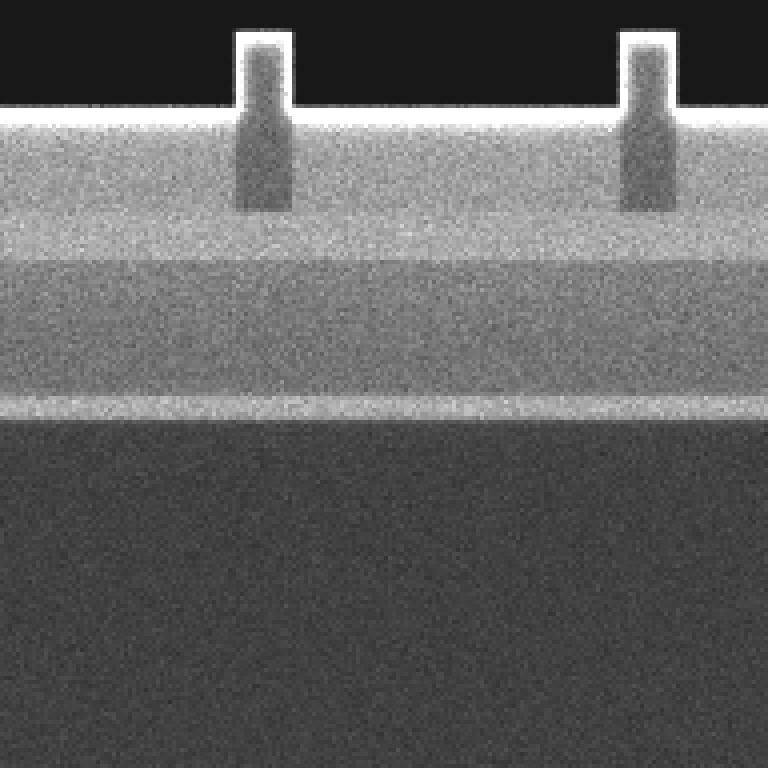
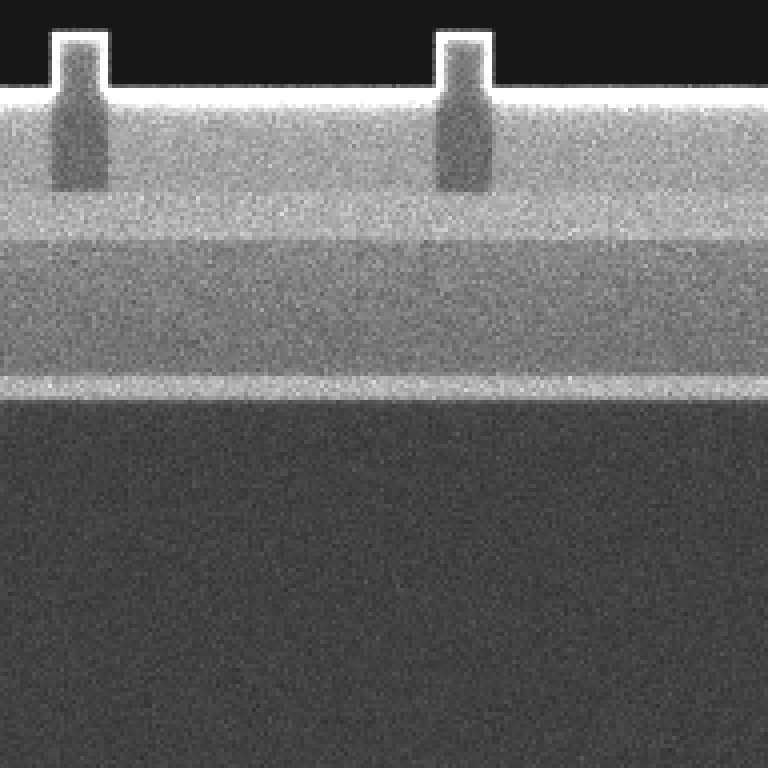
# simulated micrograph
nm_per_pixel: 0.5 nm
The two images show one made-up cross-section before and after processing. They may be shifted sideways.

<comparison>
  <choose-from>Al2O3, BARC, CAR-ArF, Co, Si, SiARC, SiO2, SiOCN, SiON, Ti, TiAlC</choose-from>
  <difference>SiARC removed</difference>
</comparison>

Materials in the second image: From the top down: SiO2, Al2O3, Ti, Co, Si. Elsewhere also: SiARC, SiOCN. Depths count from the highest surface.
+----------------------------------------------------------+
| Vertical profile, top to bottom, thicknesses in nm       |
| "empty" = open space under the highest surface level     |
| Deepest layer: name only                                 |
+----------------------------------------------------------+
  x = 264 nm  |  empty 28, SiO2 52, Al2O3 24, Ti 68, Co 12, Si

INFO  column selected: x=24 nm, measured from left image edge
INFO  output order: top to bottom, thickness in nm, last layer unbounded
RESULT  empty 28, SiO2 52, Al2O3 24, Ti 68, Co 12, Si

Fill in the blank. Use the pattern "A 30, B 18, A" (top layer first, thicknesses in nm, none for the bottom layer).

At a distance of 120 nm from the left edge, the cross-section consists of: empty 28, SiO2 52, Al2O3 24, Ti 68, Co 12, Si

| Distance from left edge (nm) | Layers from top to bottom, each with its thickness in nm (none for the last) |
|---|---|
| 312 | empty 28, SiO2 52, Al2O3 24, Ti 68, Co 12, Si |